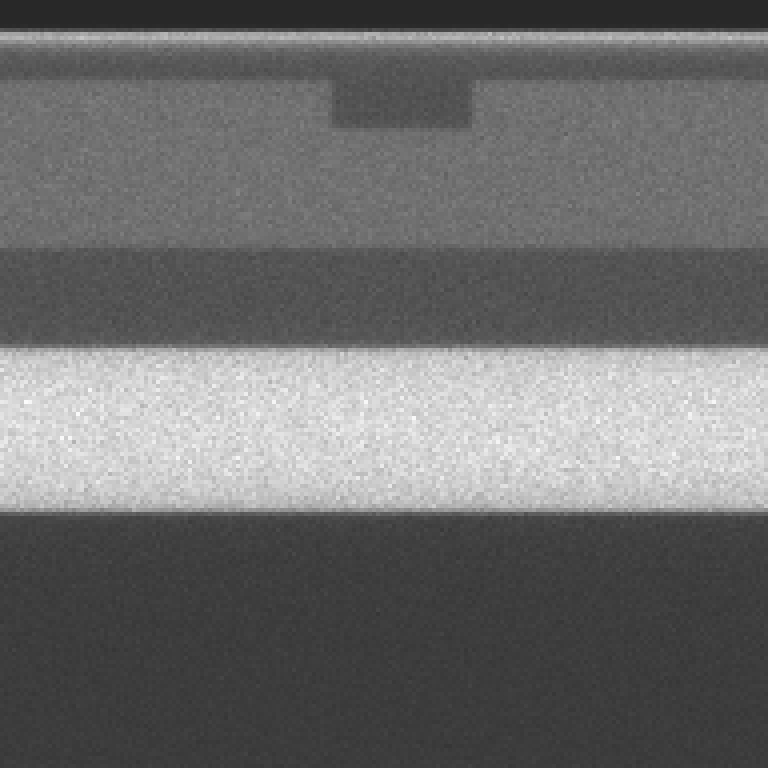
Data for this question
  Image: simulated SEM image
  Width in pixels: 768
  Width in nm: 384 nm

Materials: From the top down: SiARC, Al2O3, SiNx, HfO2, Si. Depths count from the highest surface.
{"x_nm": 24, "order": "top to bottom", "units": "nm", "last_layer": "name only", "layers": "SiARC 24, Al2O3 84, SiNx 50, HfO2 82, Si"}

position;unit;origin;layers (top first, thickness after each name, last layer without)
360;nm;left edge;SiARC 24, Al2O3 84, SiNx 50, HfO2 82, Si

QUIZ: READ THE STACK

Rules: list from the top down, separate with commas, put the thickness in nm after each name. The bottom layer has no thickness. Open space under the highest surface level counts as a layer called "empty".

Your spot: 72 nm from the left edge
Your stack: SiARC 24, Al2O3 84, SiNx 50, HfO2 82, Si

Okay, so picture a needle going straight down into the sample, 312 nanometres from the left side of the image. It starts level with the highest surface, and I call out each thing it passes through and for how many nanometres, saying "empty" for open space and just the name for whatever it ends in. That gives SiARC 24, Al2O3 84, SiNx 50, HfO2 82, Si